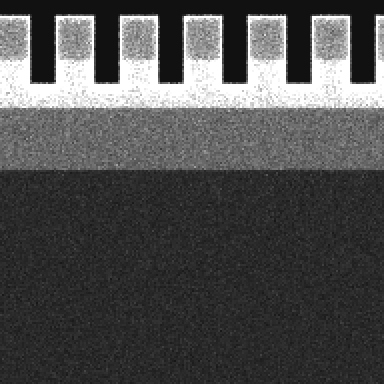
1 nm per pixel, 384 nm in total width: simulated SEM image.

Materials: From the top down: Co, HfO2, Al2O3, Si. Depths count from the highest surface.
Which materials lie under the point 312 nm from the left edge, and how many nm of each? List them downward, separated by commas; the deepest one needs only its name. Co 44, HfO2 48, Al2O3 62, Si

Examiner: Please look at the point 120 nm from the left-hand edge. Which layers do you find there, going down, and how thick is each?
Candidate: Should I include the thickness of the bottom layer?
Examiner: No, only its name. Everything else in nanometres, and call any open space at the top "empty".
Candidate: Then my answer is Co 44, HfO2 48, Al2O3 62, Si